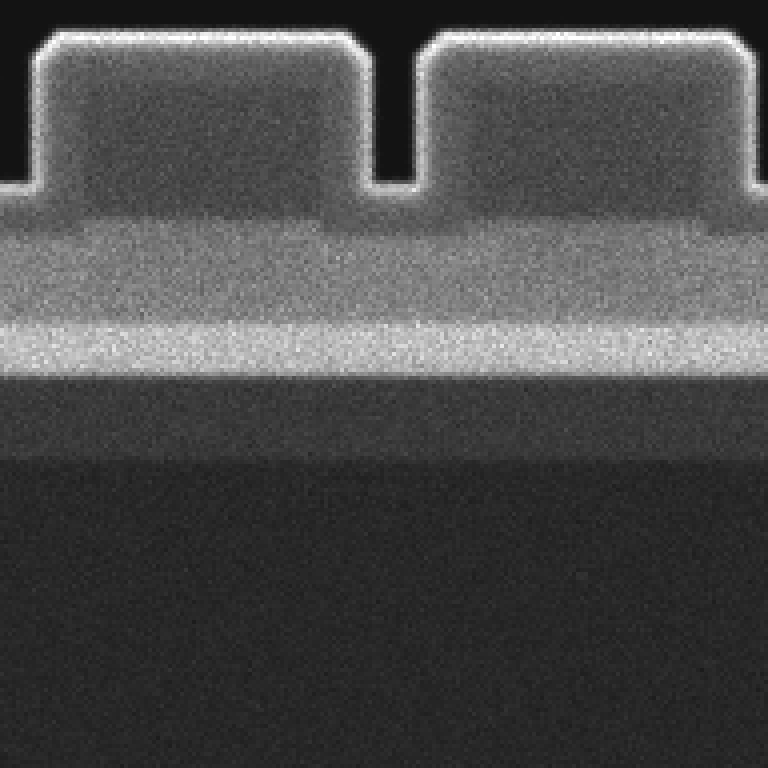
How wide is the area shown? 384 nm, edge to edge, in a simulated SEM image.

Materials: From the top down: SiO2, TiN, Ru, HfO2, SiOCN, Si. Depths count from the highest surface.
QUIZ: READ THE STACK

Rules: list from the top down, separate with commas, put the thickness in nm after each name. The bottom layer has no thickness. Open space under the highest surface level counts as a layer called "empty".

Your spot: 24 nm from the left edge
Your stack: empty 4, SiO2 98, Ru 44, HfO2 26, SiOCN 42, Si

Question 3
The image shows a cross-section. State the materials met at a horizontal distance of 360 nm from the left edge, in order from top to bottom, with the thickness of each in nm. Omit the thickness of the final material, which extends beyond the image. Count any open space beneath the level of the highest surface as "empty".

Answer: SiO2 102, Ru 44, HfO2 26, SiOCN 42, Si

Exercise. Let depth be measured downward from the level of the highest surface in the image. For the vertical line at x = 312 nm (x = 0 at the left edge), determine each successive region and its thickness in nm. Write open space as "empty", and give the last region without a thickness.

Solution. SiO2 26, TiN 68, Ru 52, HfO2 26, SiOCN 42, Si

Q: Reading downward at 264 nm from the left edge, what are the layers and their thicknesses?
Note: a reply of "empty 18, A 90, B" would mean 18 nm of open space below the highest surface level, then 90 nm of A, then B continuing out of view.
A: SiO2 26, TiN 68, Ru 52, HfO2 26, SiOCN 42, Si